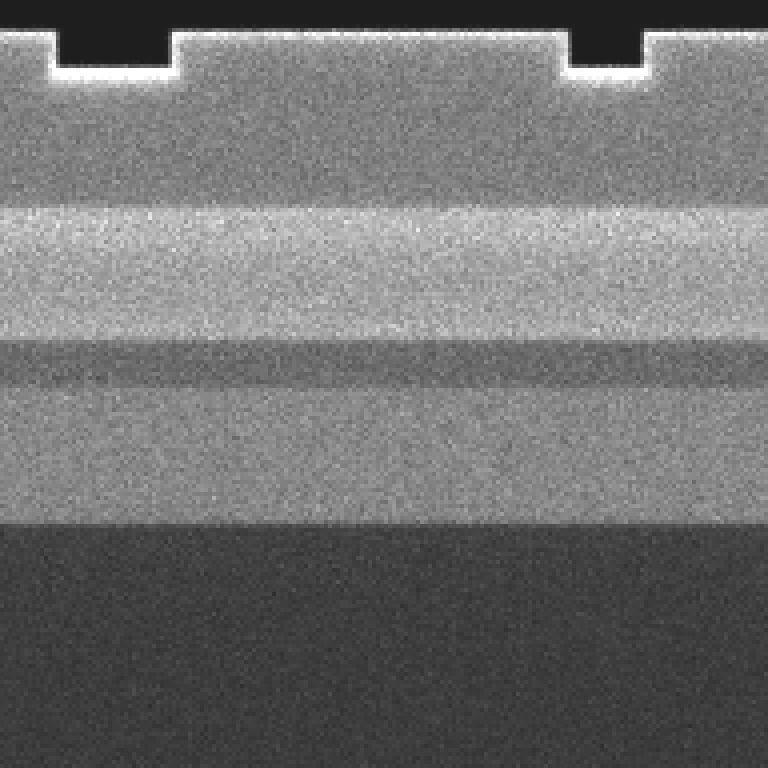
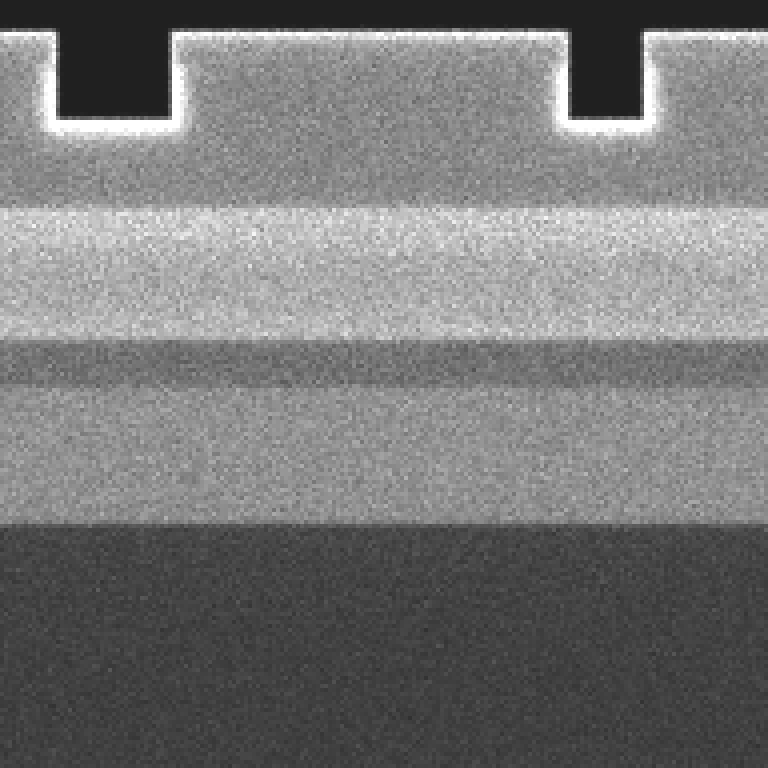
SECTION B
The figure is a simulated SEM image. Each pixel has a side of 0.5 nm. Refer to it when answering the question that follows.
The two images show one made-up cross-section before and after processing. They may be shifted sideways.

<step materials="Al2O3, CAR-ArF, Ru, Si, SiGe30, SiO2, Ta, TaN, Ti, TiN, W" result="removed SiO2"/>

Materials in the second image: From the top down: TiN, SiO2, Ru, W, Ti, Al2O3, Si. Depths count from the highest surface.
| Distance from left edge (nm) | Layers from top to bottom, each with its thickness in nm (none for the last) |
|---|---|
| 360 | TiN 18, SiO2 70, Ru 12, W 54, Ti 24, Al2O3 68, Si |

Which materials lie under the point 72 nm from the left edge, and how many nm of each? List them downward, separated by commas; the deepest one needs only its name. empty 44, SiO2 44, Ru 12, W 54, Ti 24, Al2O3 68, Si